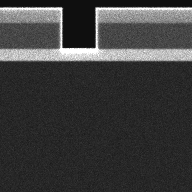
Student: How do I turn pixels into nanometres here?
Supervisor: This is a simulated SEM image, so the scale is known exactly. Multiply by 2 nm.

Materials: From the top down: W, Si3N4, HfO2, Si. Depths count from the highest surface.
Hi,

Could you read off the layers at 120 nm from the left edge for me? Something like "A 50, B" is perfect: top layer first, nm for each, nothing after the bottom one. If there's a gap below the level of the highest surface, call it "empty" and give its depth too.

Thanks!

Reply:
W 30, Si3N4 52, HfO2 24, Si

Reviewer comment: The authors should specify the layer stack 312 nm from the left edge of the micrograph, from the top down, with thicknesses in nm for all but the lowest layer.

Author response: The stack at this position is W 30, Si3N4 52, HfO2 24, Si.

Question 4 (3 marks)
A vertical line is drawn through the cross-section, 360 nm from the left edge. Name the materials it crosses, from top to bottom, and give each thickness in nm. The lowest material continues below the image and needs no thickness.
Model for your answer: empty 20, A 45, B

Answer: W 30, Si3N4 52, HfO2 24, Si